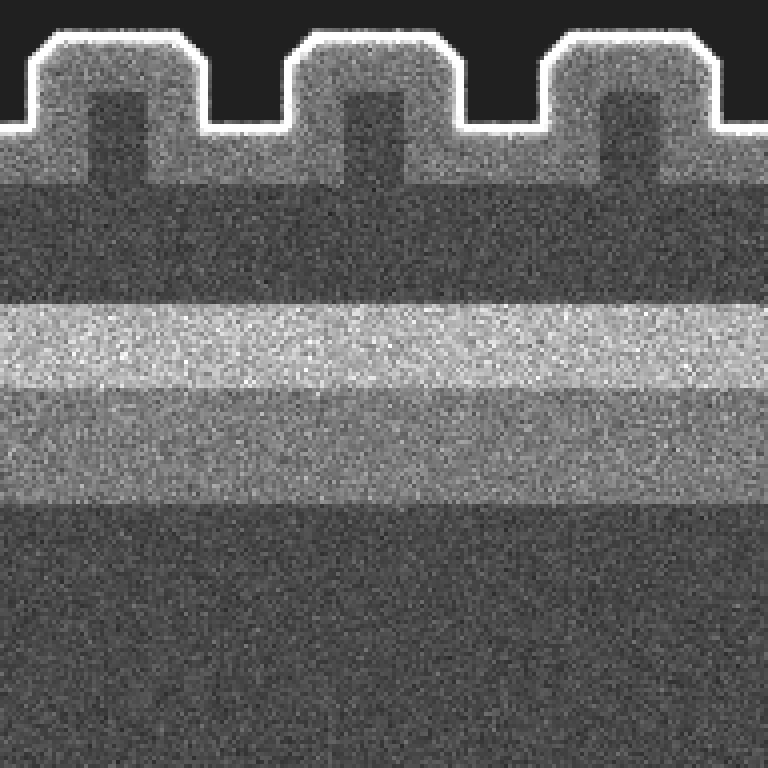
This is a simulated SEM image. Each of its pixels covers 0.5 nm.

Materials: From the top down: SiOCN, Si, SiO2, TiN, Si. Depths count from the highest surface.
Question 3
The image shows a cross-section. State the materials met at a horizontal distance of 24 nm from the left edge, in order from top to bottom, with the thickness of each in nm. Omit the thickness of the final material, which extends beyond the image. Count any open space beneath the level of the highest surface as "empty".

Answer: empty 4, SiOCN 72, Si 60, SiO2 42, TiN 58, Si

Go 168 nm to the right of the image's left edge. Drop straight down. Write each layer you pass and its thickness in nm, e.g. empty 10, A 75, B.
SiOCN 76, Si 60, SiO2 42, TiN 58, Si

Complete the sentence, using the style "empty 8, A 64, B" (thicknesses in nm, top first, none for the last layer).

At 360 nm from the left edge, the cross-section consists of empty 46, SiOCN 30, Si 60, SiO2 42, TiN 58, Si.